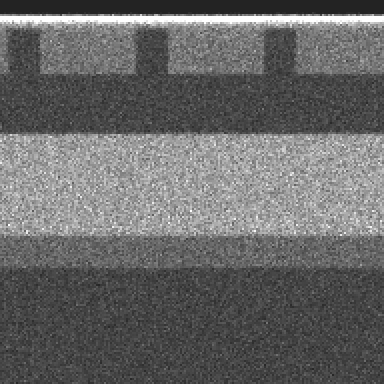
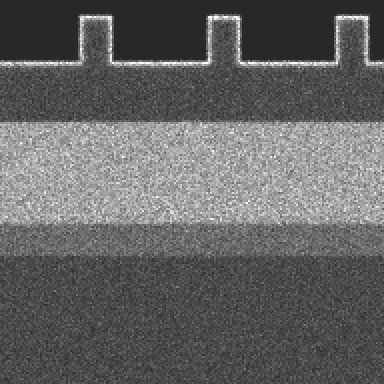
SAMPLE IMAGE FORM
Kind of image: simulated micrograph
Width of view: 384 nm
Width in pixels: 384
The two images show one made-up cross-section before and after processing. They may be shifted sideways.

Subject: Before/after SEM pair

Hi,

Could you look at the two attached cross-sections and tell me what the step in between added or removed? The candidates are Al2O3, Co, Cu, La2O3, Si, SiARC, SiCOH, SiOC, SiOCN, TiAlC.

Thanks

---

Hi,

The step removed SiARC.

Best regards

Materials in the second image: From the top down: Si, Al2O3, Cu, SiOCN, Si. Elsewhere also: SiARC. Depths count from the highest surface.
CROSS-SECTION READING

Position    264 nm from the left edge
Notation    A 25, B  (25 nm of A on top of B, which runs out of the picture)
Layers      empty 46, Si 60, Al2O3 78, Cu 24, SiOCN 32, Si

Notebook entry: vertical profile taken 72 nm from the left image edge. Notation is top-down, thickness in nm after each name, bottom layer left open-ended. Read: empty 46, Si 60, Al2O3 78, Cu 24, SiOCN 32, Si